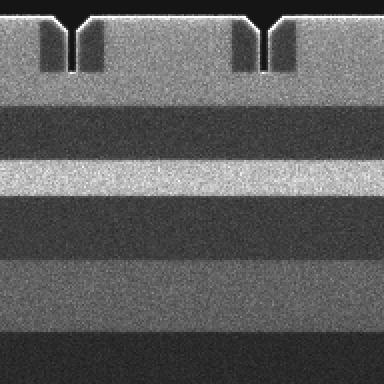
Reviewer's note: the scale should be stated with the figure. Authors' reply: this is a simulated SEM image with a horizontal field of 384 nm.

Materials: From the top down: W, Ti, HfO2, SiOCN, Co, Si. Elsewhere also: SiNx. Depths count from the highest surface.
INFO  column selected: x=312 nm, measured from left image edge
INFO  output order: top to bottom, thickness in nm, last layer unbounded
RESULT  W 90, Ti 54, HfO2 36, SiOCN 64, Co 72, Si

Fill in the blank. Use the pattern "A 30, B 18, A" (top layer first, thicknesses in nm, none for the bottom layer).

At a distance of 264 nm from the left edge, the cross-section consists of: empty 56, W 34, Ti 54, HfO2 36, SiOCN 64, Co 72, Si